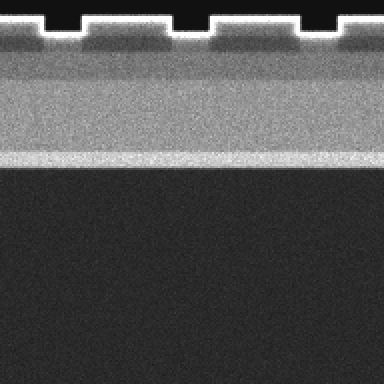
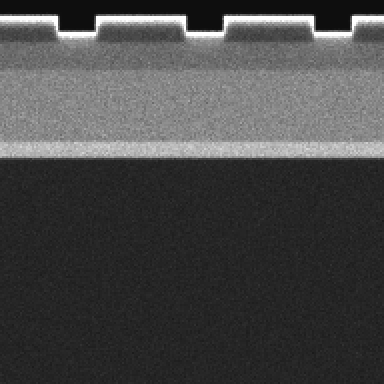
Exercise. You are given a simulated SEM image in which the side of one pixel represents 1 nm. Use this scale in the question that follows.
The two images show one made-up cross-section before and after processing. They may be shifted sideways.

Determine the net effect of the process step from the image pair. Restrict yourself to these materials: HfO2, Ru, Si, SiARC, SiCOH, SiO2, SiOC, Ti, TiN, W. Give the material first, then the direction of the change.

SiO2: removed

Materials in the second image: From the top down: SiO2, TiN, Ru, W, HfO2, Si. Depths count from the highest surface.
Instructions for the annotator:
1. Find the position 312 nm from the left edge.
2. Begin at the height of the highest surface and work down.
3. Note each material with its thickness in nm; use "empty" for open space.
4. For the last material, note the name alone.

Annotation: SiO2 10, TiN 16, Ru 28, W 72, HfO2 16, Si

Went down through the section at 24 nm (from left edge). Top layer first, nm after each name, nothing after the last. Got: SiO2 10, TiN 16, Ru 28, W 72, HfO2 16, Si